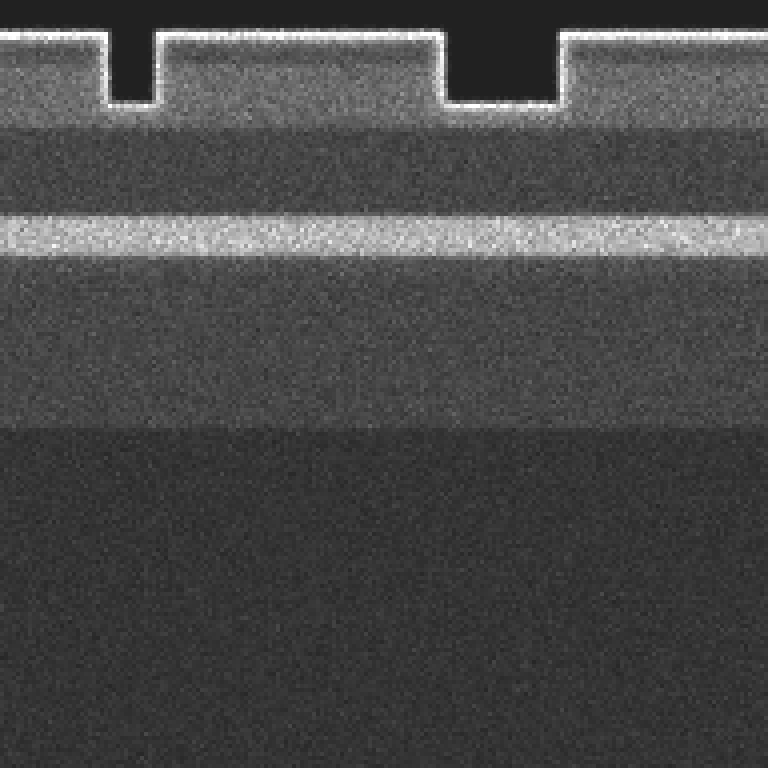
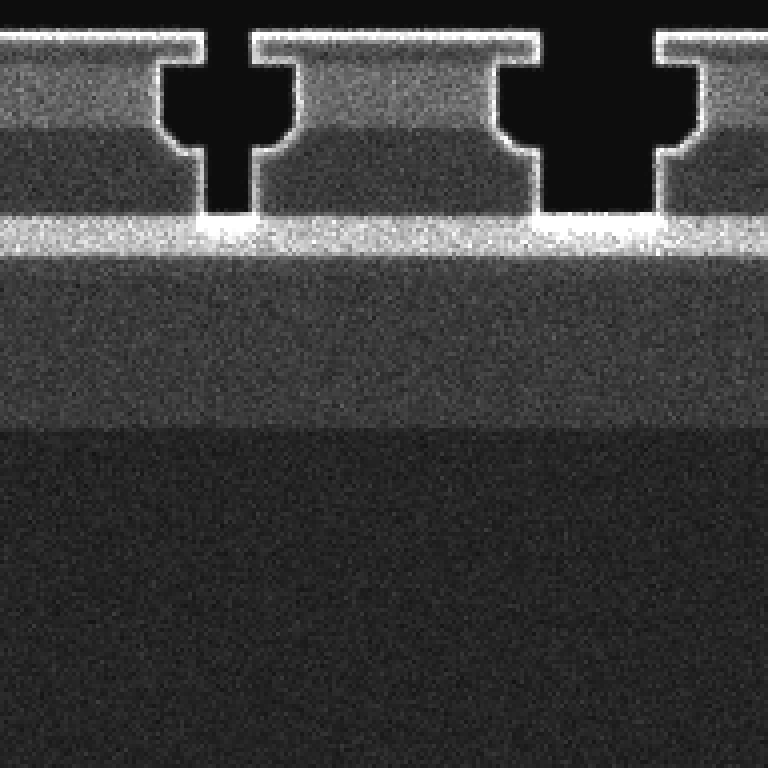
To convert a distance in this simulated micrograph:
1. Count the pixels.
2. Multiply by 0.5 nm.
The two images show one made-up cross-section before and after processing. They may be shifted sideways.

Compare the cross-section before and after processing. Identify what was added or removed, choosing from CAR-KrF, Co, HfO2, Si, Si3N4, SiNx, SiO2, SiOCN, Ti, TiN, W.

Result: Co and SiOCN removed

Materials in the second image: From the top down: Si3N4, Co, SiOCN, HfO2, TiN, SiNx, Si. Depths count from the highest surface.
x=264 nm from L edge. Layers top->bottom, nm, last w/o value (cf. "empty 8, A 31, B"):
Si3N4 16, empty 42, SiOCN 34, HfO2 20, TiN 10, SiNx 76, Si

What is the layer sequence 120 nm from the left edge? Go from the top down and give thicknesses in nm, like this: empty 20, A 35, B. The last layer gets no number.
empty 92, HfO2 20, TiN 10, SiNx 76, Si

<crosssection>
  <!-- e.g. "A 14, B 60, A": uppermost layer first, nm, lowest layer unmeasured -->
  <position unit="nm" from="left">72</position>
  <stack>Si3N4 16, Co 32, SiOCN 44, HfO2 20, TiN 10, SiNx 76, Si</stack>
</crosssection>